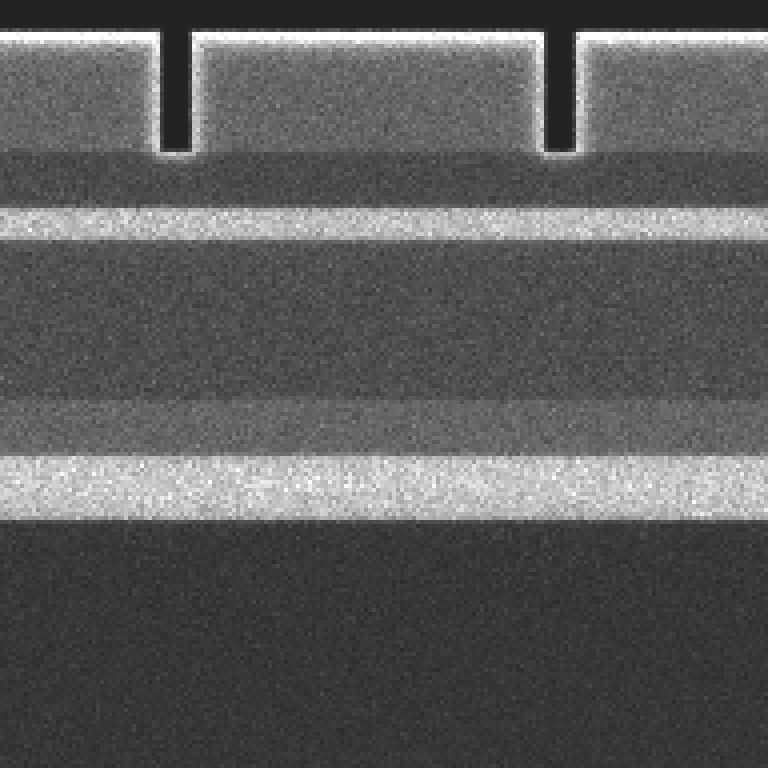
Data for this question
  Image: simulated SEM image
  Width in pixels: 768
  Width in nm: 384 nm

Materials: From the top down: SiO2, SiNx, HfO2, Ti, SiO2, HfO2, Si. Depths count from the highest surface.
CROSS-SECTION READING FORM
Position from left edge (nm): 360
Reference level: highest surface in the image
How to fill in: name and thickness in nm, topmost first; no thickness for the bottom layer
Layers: SiO2 60, SiNx 28, HfO2 16, Ti 80, SiO2 28, HfO2 32, Si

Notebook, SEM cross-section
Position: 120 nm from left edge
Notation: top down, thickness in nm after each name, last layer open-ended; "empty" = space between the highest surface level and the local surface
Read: SiO2 60, SiNx 28, HfO2 16, Ti 80, SiO2 28, HfO2 32, Si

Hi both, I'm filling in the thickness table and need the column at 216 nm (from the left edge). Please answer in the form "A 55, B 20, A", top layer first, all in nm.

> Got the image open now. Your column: SiO2 60, SiNx 28, HfO2 16, Ti 80, SiO2 28, HfO2 32, Si